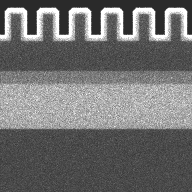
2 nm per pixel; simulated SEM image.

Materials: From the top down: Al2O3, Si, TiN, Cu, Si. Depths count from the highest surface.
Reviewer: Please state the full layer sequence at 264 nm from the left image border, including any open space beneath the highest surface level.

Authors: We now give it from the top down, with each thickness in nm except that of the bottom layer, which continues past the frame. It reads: empty 54, Al2O3 12, Si 60, TiN 26, Cu 90, Si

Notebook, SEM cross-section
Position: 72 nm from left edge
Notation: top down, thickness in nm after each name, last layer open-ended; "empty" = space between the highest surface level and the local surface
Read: empty 54, Al2O3 12, Si 60, TiN 26, Cu 90, Si